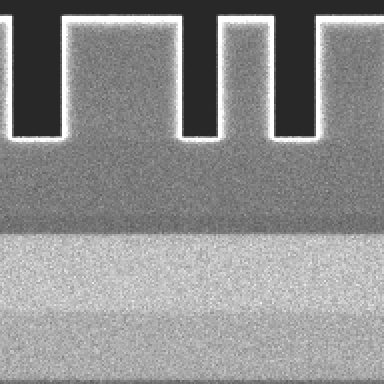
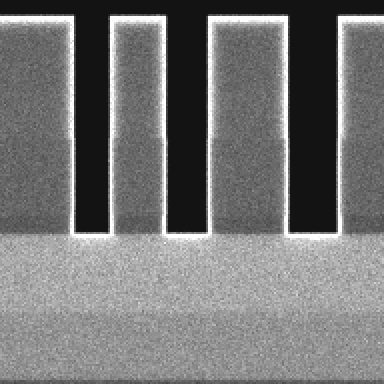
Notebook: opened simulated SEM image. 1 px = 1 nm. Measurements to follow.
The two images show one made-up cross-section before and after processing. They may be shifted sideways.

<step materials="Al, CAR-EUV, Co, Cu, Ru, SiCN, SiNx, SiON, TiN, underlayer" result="removed SiNx and TiN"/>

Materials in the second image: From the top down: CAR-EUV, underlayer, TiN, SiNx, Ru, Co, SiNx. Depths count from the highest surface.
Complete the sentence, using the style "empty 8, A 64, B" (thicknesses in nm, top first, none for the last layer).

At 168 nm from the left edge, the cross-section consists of empty 218, Ru 78, Co 68, SiNx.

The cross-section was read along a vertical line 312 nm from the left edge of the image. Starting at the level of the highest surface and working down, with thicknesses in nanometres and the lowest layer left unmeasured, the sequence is empty 218, Ru 78, Co 68, SiNx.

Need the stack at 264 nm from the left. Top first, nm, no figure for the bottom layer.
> CAR-EUV 74, underlayer 48, TiN 78, SiNx 18, Ru 78, Co 68, SiNx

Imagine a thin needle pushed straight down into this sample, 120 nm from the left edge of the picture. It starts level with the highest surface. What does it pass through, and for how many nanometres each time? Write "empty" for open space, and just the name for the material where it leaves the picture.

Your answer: CAR-EUV 74, underlayer 48, TiN 78, SiNx 18, Ru 78, Co 68, SiNx